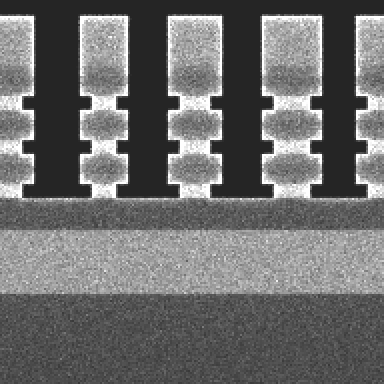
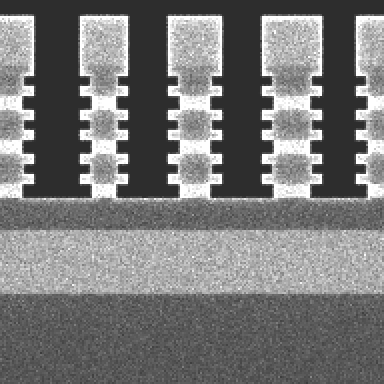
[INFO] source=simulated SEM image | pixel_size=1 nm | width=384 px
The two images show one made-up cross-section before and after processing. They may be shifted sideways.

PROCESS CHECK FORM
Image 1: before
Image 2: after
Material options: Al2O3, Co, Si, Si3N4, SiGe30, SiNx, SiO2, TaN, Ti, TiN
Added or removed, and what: removed, SiGe30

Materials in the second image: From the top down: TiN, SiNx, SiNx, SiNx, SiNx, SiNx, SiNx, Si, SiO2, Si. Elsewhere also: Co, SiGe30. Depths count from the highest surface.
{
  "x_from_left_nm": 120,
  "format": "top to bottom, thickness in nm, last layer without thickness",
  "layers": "TiN 50, SiNx 10, empty 10, SiNx 10, empty 14, SiNx 10, empty 10, SiNx 10, empty 14, SiNx 10, empty 10, SiNx 10, empty 14, Si 32, SiO2 64, Si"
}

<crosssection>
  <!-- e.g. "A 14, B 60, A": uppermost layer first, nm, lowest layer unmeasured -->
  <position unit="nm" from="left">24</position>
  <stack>TiN 50, SiNx 10, empty 10, SiNx 10, empty 14, SiNx 10, empty 10, SiNx 10, empty 14, SiNx 10, empty 10, SiNx 10, empty 14, Si 32, SiO2 64, Si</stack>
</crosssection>